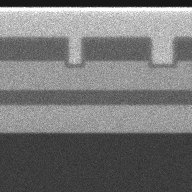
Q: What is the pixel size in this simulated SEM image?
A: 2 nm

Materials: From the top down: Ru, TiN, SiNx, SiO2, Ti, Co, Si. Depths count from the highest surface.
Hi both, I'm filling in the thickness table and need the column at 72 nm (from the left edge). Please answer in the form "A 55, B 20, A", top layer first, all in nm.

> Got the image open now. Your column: Ru 58, TiN 8, SiNx 40, SiO2 58, Ti 30, Co 56, Si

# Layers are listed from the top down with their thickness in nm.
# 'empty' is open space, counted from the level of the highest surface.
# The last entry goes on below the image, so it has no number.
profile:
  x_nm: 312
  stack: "Ru 112, TiN 8, SiO2 44, Ti 30, Co 56, Si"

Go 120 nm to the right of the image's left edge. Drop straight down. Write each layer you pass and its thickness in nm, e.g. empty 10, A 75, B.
Ru 58, TiN 8, SiNx 40, SiO2 58, Ti 30, Co 56, Si